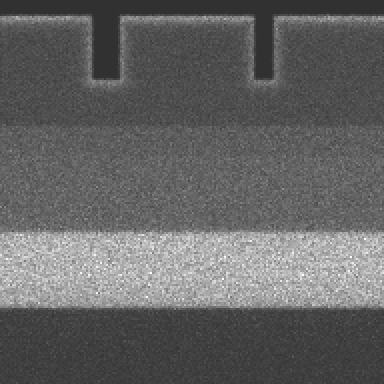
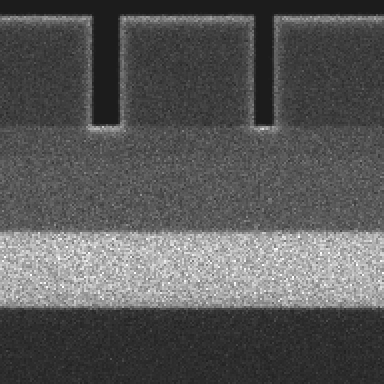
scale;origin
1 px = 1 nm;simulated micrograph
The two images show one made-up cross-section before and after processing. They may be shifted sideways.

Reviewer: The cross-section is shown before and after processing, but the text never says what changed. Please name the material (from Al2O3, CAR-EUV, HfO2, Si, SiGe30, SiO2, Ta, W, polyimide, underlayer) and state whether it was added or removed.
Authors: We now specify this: underlayer, removed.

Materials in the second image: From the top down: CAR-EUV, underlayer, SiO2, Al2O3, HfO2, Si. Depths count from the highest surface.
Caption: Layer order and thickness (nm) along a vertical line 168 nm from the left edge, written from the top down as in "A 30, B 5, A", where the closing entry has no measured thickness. CAR-EUV 64, underlayer 46, SiO2 30, Al2O3 76, HfO2 76, Si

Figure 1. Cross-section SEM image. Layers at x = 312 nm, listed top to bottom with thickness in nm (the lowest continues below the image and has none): CAR-EUV 64, underlayer 46, SiO2 30, Al2O3 76, HfO2 76, Si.